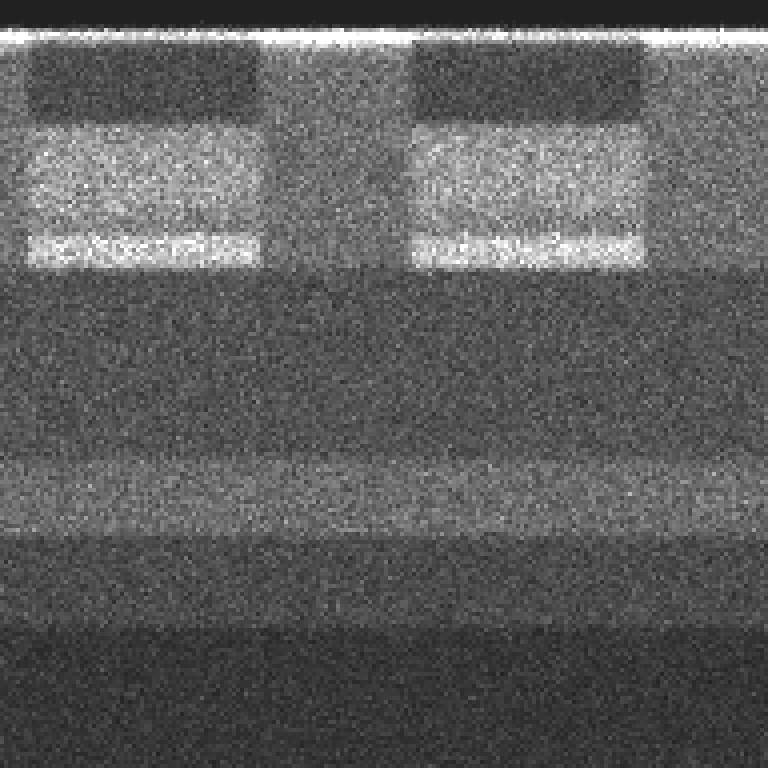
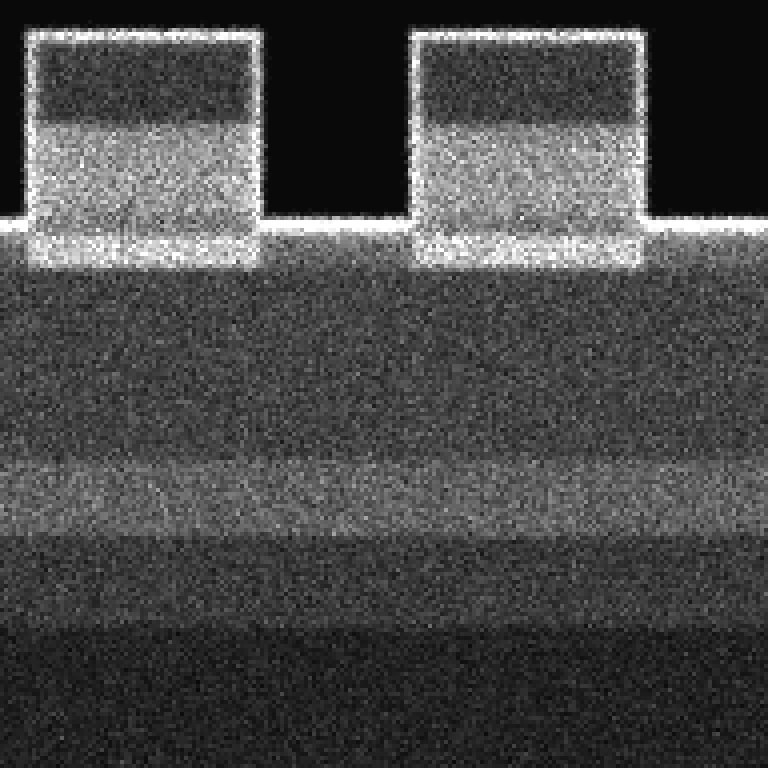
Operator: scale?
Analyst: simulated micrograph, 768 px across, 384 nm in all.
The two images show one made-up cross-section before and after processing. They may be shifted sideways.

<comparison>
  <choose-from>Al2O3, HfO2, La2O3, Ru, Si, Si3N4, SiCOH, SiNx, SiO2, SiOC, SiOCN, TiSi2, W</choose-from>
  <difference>Al2O3 removed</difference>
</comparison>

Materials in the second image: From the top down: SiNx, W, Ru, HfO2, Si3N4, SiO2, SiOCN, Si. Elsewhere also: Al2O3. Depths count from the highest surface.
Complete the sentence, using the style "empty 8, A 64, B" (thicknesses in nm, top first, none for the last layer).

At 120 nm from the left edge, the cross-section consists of SiNx 46, W 44, Ru 12, HfO2 16, Si3N4 96, SiO2 38, SiOCN 46, Si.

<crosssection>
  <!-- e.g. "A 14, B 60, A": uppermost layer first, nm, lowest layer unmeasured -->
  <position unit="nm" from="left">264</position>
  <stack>SiNx 46, W 44, Ru 12, HfO2 16, Si3N4 96, SiO2 38, SiOCN 46, Si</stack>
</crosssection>